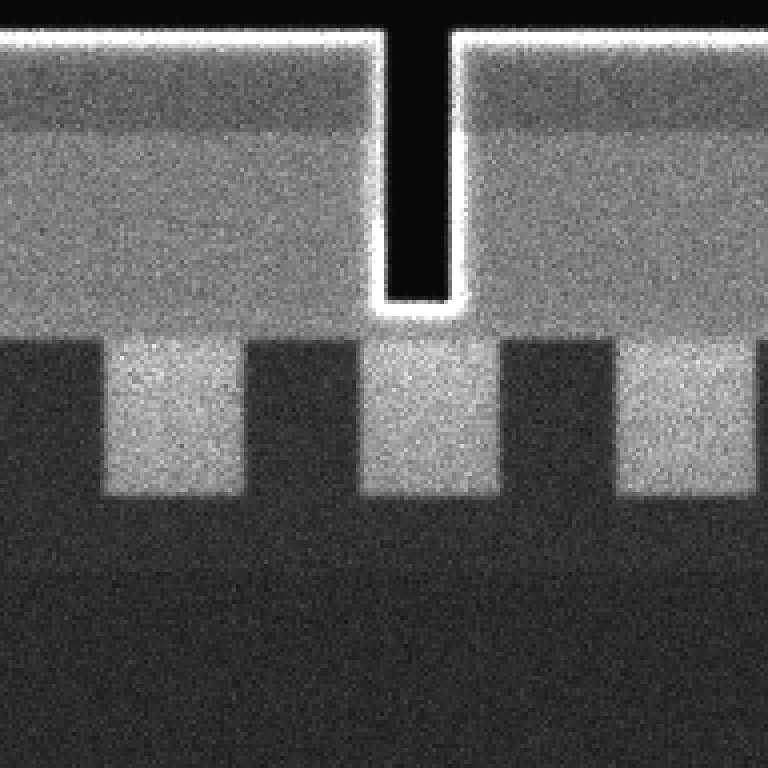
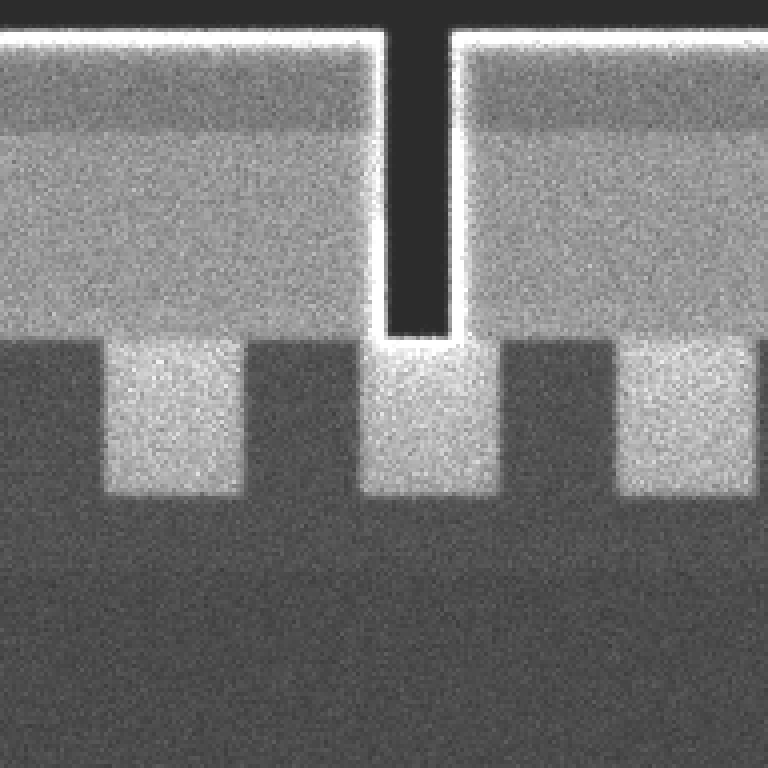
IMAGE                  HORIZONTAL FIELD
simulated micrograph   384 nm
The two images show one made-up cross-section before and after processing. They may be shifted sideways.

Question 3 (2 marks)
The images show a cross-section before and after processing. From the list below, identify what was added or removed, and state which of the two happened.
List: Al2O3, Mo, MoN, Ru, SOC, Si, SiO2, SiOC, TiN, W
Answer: Al2O3 was removed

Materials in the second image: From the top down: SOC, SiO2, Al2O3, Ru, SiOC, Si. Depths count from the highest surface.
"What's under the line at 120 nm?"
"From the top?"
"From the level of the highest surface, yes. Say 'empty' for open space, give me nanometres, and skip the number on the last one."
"SOC 50, SiO2 86, Al2O3 18, Ru 78, SiOC 38, Si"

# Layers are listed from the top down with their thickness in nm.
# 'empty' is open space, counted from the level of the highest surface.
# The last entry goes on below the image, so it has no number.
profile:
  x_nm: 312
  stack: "SOC 50, SiO2 86, Al2O3 18, Ru 78, SiOC 38, Si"